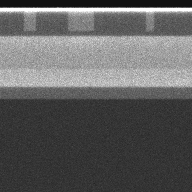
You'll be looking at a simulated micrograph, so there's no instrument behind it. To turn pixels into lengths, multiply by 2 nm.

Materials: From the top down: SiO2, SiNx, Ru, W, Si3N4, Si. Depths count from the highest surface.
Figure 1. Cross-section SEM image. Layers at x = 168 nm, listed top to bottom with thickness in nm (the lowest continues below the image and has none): SiO2 46, SiNx 10, Ru 66, W 36, Si3N4 24, Si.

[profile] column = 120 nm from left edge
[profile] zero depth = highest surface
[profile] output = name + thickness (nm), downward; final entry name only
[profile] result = SiO2 6, SiNx 50, Ru 66, W 36, Si3N4 24, Si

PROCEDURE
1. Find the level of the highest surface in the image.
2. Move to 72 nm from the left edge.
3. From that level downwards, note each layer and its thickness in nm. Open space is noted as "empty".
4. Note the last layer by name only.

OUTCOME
SiO2 6, SiNx 50, Ru 66, W 36, Si3N4 24, Si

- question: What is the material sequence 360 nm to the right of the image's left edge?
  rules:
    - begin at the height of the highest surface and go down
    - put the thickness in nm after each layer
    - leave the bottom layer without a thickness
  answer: SiO2 6, SiNx 50, Ru 66, W 36, Si3N4 24, Si